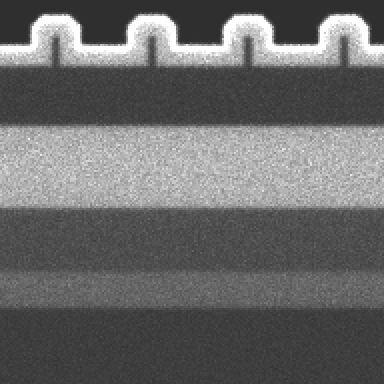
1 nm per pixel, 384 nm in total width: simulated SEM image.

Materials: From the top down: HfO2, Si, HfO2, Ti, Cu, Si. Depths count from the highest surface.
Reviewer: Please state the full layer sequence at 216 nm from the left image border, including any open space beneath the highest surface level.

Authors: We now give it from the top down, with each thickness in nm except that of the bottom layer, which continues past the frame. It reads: empty 30, HfO2 20, Si 60, HfO2 82, Ti 64, Cu 36, Si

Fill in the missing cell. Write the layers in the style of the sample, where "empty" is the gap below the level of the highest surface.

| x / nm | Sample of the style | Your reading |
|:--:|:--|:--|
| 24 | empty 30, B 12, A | empty 30, HfO2 20, Si 60, HfO2 82, Ti 64, Cu 36, Si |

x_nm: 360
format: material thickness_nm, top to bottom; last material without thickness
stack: empty 4, HfO2 46, Si 60, HfO2 82, Ti 64, Cu 36, Si